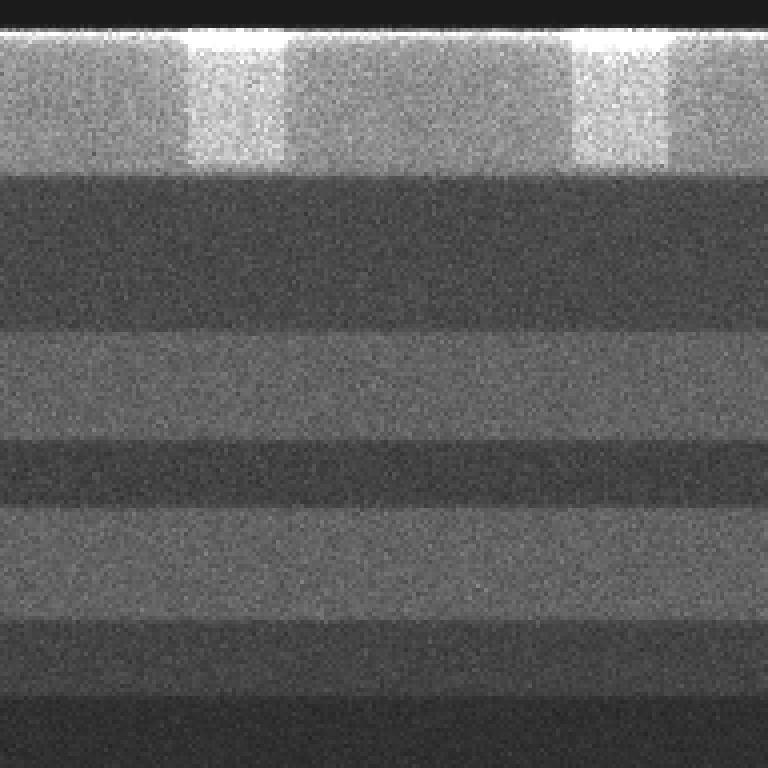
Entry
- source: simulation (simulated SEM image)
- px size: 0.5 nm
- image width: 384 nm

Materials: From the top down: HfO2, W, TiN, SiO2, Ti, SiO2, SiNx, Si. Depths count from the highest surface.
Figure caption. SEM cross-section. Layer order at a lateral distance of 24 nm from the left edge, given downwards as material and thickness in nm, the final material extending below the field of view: W 72, TiN 78, SiO2 54, Ti 34, SiO2 56, SiNx 38, Si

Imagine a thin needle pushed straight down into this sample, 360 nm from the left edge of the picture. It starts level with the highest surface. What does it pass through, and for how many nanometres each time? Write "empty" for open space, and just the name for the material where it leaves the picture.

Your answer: W 72, TiN 78, SiO2 54, Ti 34, SiO2 56, SiNx 38, Si